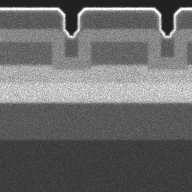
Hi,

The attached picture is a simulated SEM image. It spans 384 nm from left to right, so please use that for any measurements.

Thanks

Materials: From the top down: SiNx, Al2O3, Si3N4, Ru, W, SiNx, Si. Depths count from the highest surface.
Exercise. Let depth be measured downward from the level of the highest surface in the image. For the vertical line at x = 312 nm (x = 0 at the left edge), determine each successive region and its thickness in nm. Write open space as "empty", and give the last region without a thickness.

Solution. empty 4, SiNx 42, Al2O3 78, Ru 26, W 40, SiNx 74, Si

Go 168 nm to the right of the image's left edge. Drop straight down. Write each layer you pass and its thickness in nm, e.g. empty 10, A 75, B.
SiNx 42, Al2O3 82, Ru 26, W 40, SiNx 74, Si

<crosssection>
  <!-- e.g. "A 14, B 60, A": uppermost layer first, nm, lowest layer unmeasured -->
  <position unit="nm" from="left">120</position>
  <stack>empty 4, SiNx 42, Al2O3 78, Ru 26, W 40, SiNx 74, Si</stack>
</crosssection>